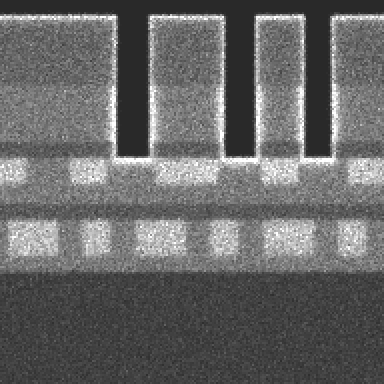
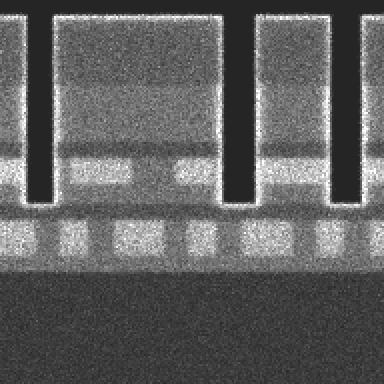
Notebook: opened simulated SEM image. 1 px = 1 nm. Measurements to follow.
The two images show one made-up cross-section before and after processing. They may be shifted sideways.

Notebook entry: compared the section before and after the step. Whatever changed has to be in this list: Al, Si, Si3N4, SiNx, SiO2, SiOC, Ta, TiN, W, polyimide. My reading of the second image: SiO2 removed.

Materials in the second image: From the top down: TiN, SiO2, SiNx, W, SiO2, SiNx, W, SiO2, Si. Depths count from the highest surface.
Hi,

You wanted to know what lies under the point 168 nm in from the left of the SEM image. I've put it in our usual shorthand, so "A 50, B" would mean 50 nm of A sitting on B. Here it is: TiN 70, SiO2 56, SiNx 16, SiO2 46, SiNx 16, SiO2 52, Si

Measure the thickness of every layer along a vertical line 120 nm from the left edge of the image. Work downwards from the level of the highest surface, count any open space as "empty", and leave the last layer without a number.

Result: TiN 70, SiO2 56, SiNx 16, W 26, SiO2 20, SiNx 16, W 36, SiO2 16, Si